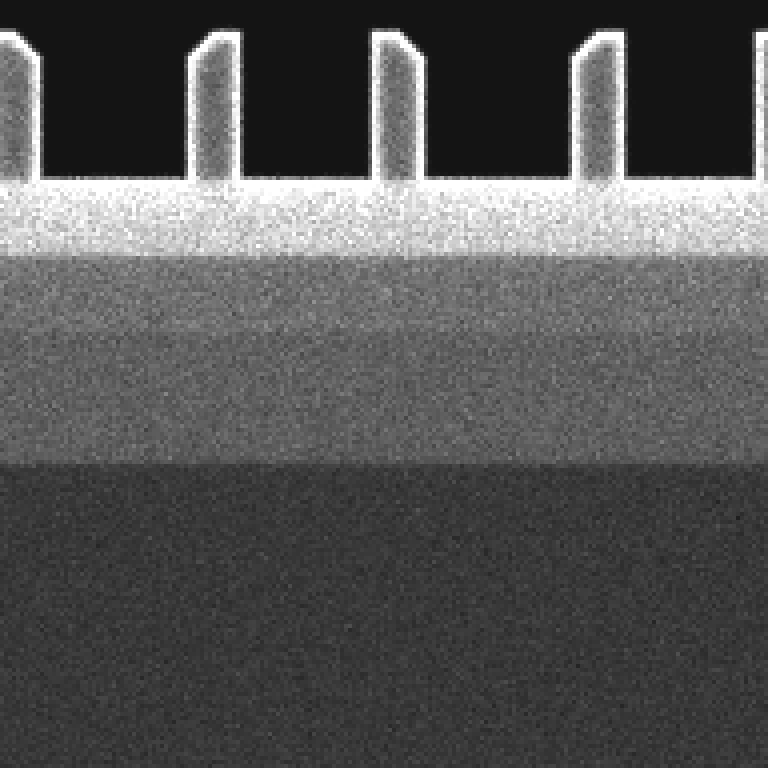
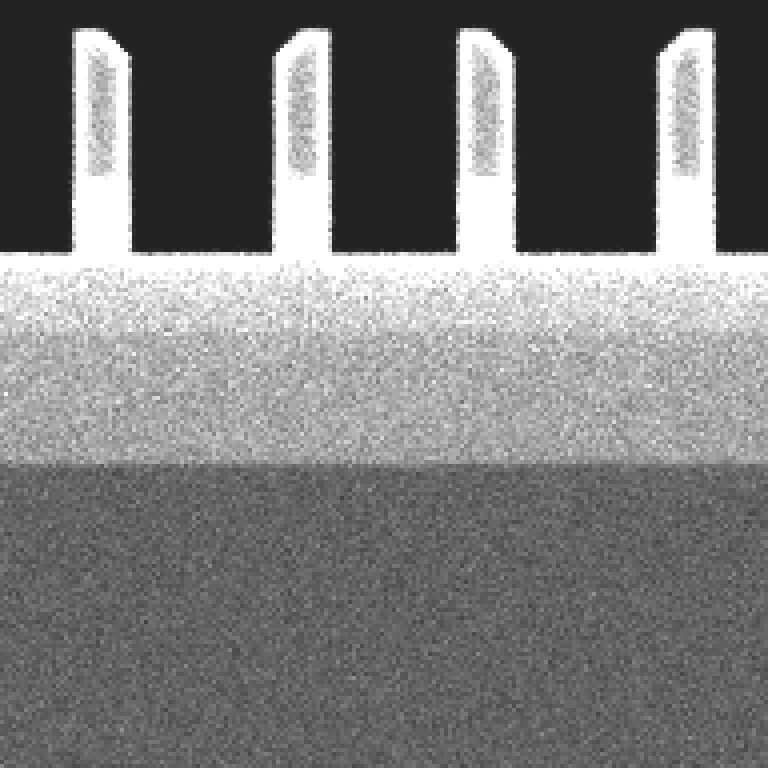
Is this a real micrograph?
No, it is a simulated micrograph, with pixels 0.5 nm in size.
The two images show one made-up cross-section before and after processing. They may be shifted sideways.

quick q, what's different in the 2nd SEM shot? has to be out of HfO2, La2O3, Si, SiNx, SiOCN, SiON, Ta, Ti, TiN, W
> W removed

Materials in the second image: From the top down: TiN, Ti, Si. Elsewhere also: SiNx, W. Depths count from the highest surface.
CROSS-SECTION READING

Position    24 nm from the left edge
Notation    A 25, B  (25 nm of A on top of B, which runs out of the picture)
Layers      empty 112, TiN 38, Ti 66, Si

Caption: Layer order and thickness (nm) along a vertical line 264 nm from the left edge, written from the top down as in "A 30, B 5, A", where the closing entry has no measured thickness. empty 112, TiN 38, Ti 66, Si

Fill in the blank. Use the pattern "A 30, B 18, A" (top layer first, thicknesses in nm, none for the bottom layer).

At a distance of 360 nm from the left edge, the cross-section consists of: empty 112, TiN 38, Ti 66, Si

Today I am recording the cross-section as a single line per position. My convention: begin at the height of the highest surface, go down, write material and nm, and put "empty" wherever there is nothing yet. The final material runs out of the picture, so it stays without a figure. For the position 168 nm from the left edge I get empty 112, TiN 38, Ti 66, Si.